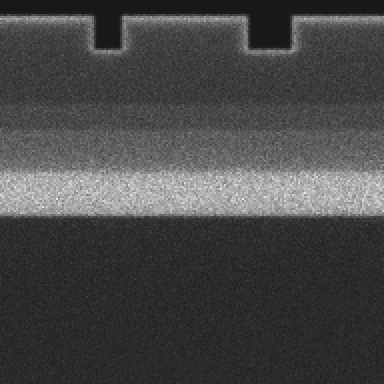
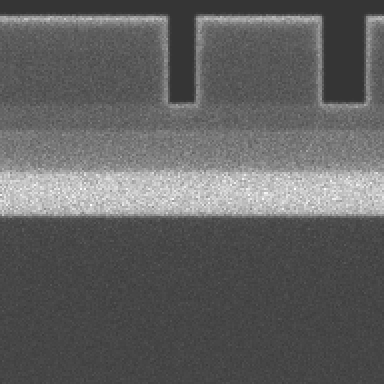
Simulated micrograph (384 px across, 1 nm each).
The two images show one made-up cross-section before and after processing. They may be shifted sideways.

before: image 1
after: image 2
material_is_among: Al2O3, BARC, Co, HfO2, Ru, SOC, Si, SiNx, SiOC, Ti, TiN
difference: SiNx, removed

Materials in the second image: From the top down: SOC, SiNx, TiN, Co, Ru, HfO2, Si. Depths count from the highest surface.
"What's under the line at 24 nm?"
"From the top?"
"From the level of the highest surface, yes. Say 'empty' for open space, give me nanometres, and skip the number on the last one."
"SOC 34, SiNx 54, TiN 26, Co 16, Ru 26, HfO2 44, Si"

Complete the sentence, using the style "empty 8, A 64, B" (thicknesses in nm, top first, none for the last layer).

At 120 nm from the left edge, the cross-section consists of SOC 34, SiNx 54, TiN 26, Co 16, Ru 26, HfO2 44, Si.